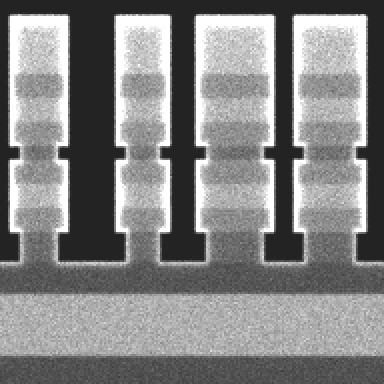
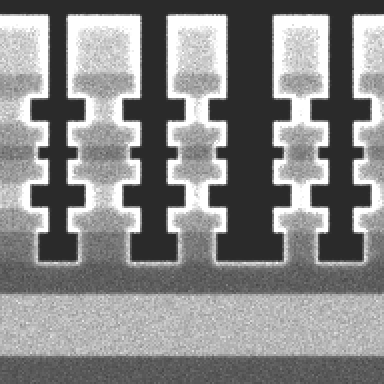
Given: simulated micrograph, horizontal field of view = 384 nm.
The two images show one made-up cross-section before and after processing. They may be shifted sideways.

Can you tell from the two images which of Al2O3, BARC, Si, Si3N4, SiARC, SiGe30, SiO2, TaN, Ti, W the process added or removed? Yes, it removed SiO2.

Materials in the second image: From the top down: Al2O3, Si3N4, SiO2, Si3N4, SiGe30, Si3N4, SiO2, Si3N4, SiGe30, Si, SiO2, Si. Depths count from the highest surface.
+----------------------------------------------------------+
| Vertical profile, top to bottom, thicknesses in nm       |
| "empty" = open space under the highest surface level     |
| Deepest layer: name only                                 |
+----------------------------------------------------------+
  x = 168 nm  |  Al2O3 58, Si3N4 24, empty 24, Si3N4 24, empty 14, Si3N4 24, empty 24, Si3N4 24, empty 30, Si 32, SiO2 62, Si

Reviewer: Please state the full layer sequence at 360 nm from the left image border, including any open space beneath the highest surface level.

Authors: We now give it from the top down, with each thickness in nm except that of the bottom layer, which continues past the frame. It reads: Al2O3 58, Si3N4 24, empty 24, Si3N4 24, empty 14, Si3N4 24, empty 24, Si3N4 24, empty 30, Si 32, SiO2 62, Si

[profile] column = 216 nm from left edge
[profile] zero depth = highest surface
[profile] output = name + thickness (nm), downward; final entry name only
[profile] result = Al2O3 58, Si3N4 24, empty 24, Si3N4 24, empty 14, Si3N4 24, empty 24, Si3N4 24, empty 30, Si 32, SiO2 62, Si